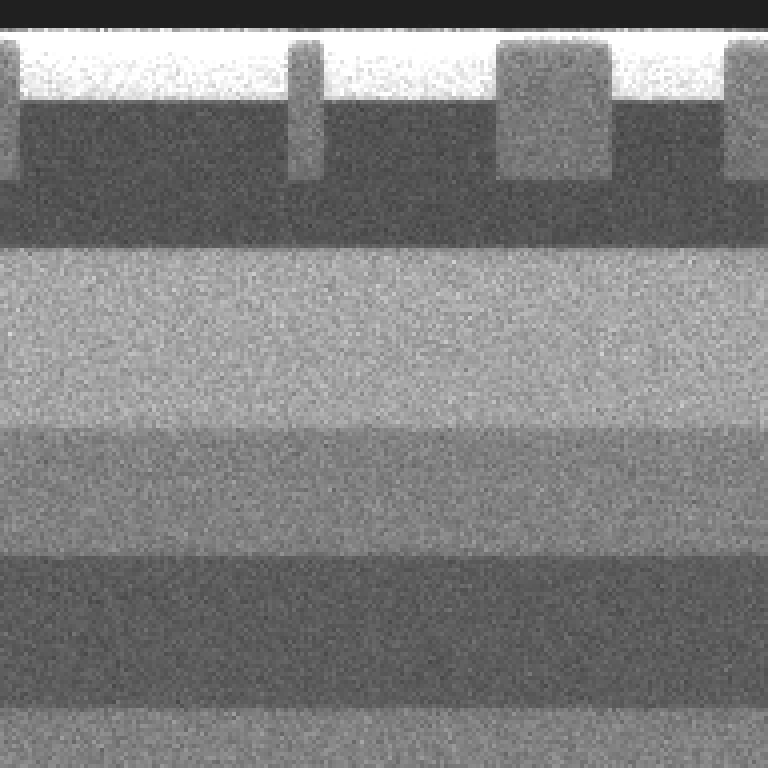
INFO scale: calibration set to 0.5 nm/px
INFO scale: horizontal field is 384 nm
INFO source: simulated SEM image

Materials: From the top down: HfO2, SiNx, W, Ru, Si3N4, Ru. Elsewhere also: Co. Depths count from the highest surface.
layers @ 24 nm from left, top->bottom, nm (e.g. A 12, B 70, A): HfO2 34, SiNx 74, W 90, Ru 64, Si3N4 76, Ru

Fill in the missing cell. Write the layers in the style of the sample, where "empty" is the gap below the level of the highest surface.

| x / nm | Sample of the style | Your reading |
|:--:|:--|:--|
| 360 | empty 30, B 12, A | HfO2 34, SiNx 74, W 90, Ru 64, Si3N4 76, Ru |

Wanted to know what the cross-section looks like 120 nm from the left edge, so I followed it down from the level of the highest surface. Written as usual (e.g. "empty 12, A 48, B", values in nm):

HfO2 34, SiNx 74, W 90, Ru 64, Si3N4 76, Ru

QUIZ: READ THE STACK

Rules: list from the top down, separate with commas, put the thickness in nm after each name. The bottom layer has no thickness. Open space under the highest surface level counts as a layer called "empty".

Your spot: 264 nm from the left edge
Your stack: Co 74, SiNx 34, W 90, Ru 64, Si3N4 76, Ru